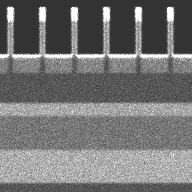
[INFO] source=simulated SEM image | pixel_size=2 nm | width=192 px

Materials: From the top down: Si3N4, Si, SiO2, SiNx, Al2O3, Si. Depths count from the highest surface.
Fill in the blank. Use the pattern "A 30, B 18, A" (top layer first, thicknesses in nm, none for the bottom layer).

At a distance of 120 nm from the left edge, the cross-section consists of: empty 94, Si3N4 36, Si 60, SiO2 26, SiNx 68, Al2O3 66, Si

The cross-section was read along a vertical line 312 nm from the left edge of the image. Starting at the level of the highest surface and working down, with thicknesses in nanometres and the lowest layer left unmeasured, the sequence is empty 94, Si3N4 36, Si 60, SiO2 26, SiNx 68, Al2O3 66, Si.